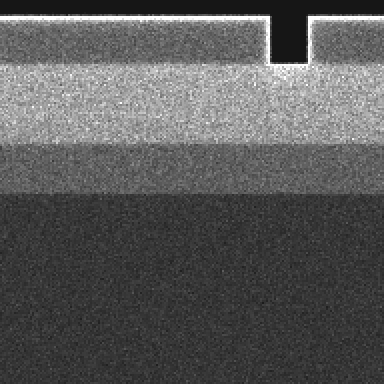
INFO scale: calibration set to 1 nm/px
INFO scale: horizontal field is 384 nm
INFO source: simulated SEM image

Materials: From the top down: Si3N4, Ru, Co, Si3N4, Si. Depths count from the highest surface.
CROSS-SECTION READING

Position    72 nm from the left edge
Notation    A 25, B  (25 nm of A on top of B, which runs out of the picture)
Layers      Si3N4 48, Ru 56, Co 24, Si3N4 50, Si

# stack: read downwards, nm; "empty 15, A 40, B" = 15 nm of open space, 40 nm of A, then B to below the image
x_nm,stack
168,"Si3N4 48, Ru 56, Co 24, Si3N4 50, Si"